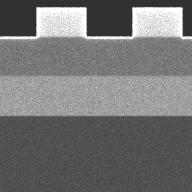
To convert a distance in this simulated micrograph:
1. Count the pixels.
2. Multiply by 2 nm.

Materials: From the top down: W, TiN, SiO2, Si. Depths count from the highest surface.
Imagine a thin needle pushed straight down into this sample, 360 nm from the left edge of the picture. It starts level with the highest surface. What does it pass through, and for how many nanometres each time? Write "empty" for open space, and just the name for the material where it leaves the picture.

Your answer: W 58, TiN 78, SiO2 80, Si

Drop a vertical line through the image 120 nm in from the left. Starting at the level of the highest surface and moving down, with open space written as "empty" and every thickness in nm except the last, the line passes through W 58, TiN 78, SiO2 80, Si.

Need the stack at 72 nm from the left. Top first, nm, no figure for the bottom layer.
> empty 58, TiN 78, SiO2 80, Si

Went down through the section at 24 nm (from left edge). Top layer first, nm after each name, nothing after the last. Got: empty 58, TiN 78, SiO2 80, Si